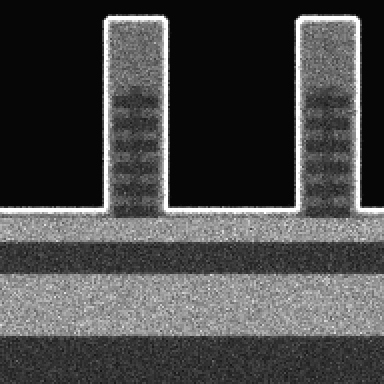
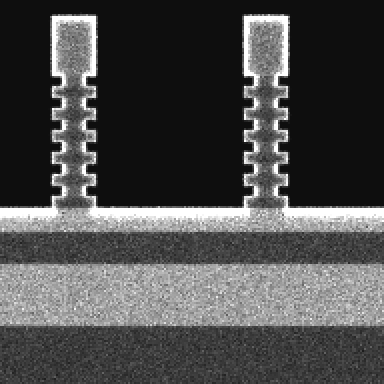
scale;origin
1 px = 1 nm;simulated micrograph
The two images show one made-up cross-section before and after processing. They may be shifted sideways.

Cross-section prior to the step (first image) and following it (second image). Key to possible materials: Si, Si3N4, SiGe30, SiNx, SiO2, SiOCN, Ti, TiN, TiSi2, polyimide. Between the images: SiOCN was removed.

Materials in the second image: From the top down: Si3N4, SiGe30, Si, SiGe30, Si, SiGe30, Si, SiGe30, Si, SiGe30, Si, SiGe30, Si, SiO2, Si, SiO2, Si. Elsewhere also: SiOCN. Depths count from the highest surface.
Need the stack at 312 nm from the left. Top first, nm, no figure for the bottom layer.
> empty 192, SiO2 24, Si 32, SiO2 62, Si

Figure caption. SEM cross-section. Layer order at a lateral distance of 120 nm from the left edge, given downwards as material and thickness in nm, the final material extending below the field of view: empty 192, SiO2 24, Si 32, SiO2 62, Si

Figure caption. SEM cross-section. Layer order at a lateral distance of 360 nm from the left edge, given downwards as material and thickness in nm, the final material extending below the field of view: empty 192, SiO2 24, Si 32, SiO2 62, Si